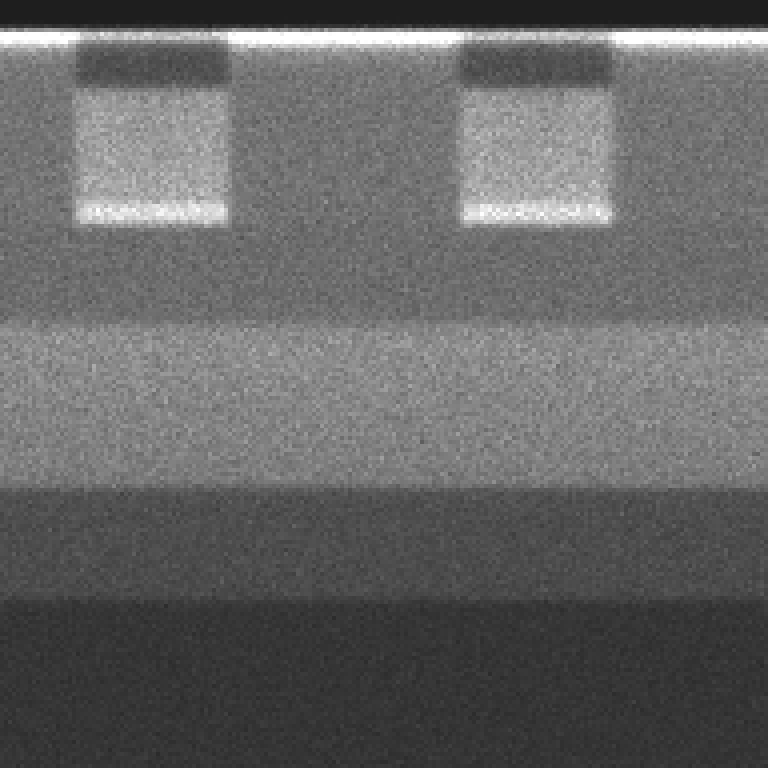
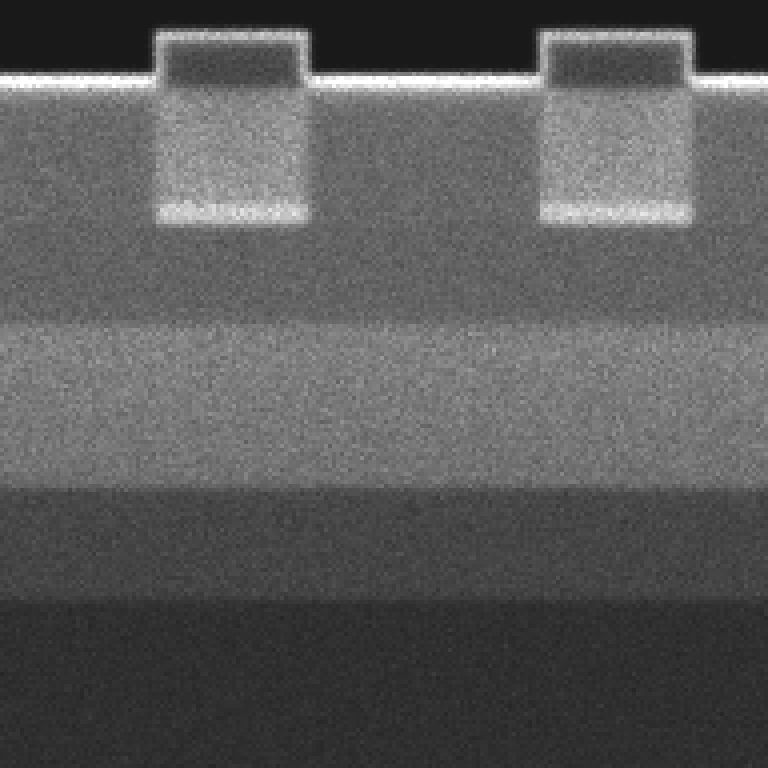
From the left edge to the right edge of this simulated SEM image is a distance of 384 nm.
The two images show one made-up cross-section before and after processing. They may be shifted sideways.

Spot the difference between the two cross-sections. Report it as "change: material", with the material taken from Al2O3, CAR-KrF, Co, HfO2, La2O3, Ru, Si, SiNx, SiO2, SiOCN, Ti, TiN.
removed: Al2O3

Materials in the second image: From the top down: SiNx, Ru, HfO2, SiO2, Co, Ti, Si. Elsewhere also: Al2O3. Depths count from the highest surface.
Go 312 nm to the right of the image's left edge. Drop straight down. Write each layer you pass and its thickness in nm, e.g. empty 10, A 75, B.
SiNx 28, Ru 58, HfO2 10, SiO2 50, Co 82, Ti 56, Si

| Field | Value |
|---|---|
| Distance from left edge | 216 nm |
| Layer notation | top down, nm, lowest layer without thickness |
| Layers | empty 22, Al2O3 74, SiO2 50, Co 82, Ti 56, Si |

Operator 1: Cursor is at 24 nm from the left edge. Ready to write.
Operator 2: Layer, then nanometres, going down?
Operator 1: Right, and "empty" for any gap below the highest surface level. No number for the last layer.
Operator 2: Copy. empty 22, Al2O3 74, SiO2 50, Co 82, Ti 56, Si